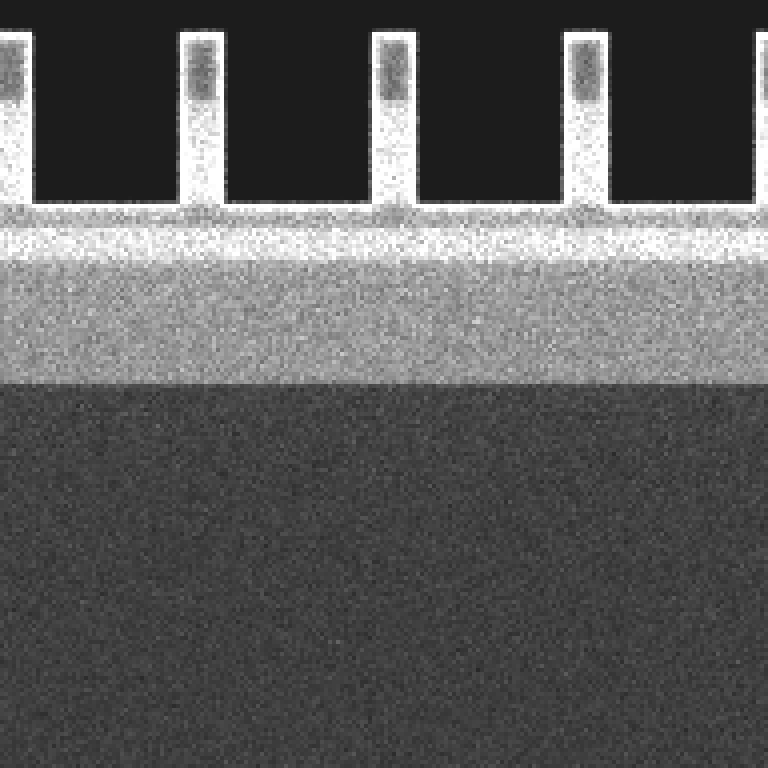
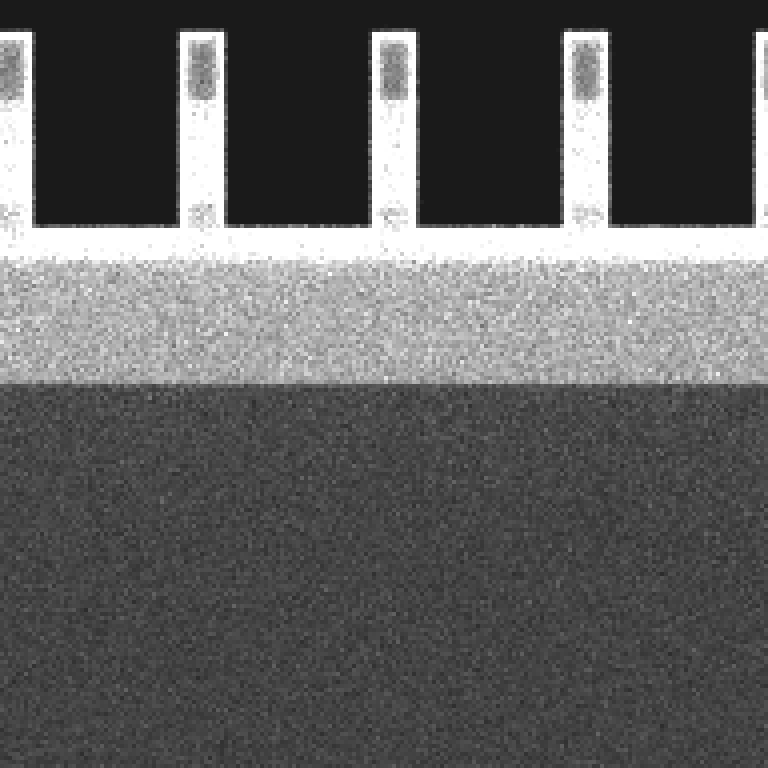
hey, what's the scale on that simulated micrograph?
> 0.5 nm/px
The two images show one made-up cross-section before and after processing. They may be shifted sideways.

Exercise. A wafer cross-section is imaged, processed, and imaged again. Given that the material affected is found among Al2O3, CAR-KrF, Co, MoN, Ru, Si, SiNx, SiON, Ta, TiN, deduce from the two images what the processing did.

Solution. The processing removed TiN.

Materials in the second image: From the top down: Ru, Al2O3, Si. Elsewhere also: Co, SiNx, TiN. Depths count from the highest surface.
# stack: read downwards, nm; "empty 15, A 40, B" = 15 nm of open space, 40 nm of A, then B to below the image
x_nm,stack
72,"empty 98, Ru 16, Al2O3 62, Si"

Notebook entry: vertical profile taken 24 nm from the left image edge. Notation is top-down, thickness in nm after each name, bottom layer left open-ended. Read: empty 98, Ru 16, Al2O3 62, Si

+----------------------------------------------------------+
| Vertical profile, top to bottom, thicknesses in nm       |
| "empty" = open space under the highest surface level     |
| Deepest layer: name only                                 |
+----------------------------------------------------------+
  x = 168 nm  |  empty 98, Ru 16, Al2O3 62, Si